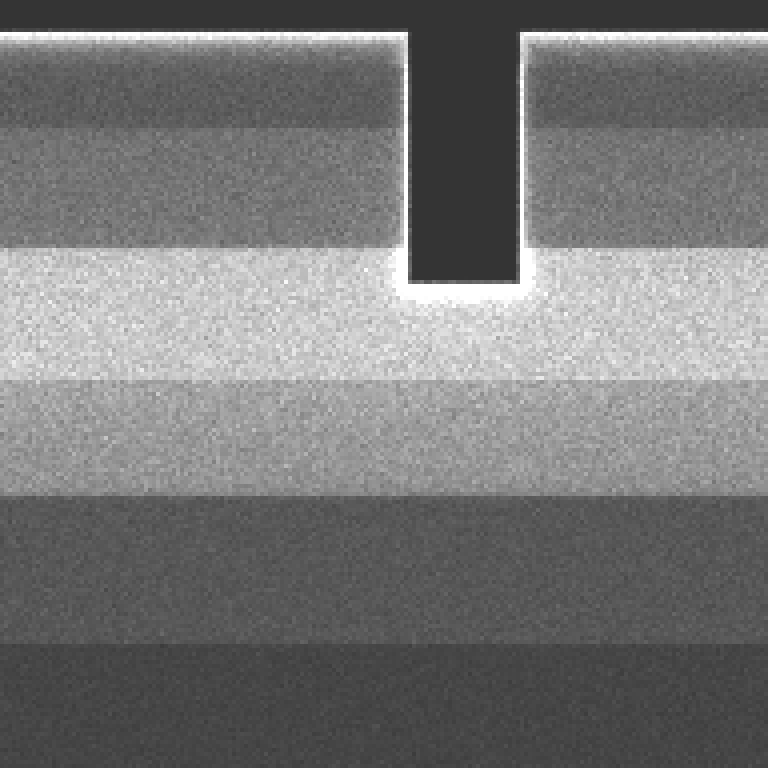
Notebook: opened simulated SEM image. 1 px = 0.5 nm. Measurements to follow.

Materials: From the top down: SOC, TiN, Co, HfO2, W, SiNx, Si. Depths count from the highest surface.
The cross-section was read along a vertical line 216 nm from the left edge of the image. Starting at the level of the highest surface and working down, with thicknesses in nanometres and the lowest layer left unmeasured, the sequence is empty 126, HfO2 48, W 58, SiNx 74, Si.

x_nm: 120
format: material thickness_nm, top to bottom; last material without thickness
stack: SOC 16, TiN 32, Co 60, HfO2 66, W 58, SiNx 74, Si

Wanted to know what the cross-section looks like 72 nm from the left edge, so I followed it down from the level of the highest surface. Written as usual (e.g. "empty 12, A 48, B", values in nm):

SOC 16, TiN 32, Co 60, HfO2 66, W 58, SiNx 74, Si